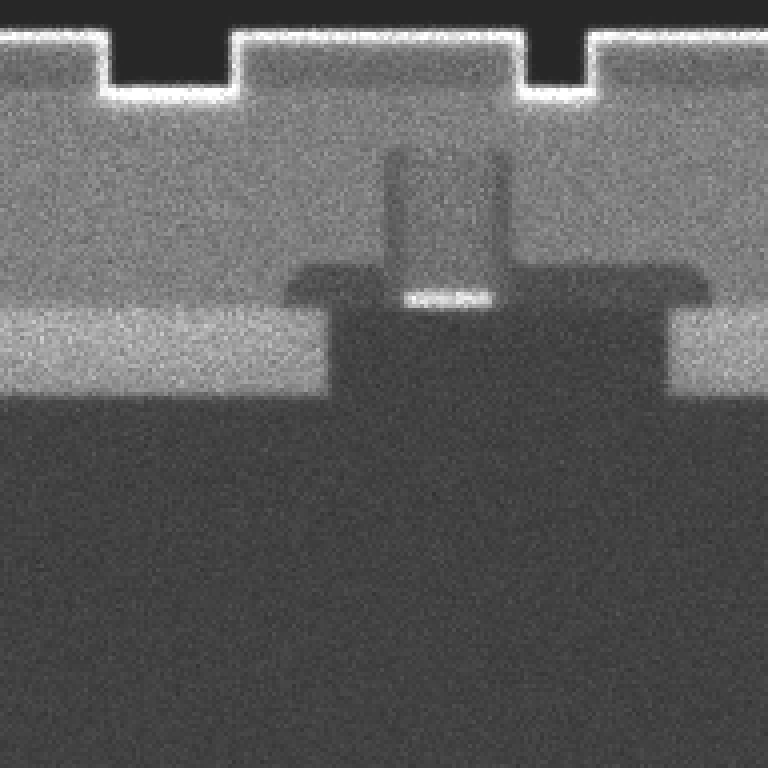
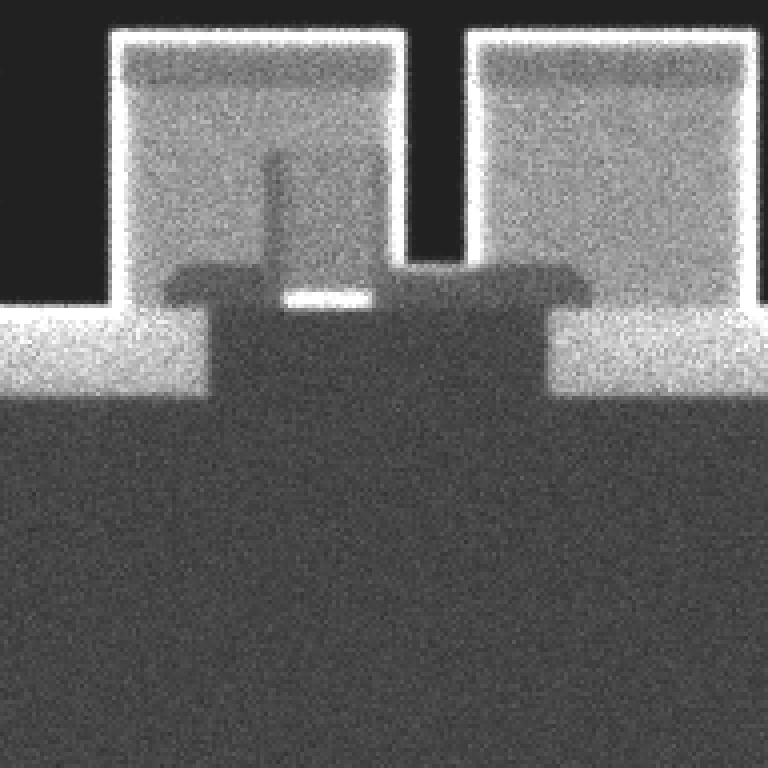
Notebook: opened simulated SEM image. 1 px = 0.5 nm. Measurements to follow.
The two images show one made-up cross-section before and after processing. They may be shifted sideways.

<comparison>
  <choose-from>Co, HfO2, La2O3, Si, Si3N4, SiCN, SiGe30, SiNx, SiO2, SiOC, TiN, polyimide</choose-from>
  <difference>SiO2 removed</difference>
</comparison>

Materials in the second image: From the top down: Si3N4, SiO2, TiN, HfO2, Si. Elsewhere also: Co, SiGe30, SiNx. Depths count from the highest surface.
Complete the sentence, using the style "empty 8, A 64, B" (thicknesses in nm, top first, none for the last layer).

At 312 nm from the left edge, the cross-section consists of Si3N4 28, SiO2 110, Co 44, Si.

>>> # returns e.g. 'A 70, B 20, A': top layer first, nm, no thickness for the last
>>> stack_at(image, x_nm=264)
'Si3N4 28, SiO2 88, SiGe30 22, Si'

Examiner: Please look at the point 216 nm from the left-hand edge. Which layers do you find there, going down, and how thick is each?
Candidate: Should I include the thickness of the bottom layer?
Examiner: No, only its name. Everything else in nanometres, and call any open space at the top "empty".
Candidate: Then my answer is empty 116, SiGe30 22, Si